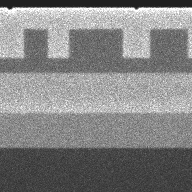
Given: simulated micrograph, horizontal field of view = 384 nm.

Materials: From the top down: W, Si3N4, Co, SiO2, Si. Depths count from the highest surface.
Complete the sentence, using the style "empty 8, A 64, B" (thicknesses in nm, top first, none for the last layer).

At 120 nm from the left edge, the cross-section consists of W 100, Si3N4 30, Co 80, SiO2 70, Si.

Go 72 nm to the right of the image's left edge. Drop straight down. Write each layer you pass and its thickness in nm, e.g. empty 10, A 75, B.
W 42, Si3N4 88, Co 80, SiO2 70, Si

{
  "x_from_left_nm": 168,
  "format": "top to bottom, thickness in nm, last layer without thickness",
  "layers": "W 42, Si3N4 88, Co 80, SiO2 70, Si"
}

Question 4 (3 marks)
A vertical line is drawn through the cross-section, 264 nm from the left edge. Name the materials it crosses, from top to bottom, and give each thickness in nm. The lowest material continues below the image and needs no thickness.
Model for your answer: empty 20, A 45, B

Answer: W 100, Si3N4 30, Co 80, SiO2 70, Si